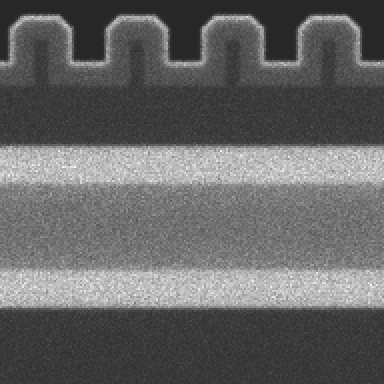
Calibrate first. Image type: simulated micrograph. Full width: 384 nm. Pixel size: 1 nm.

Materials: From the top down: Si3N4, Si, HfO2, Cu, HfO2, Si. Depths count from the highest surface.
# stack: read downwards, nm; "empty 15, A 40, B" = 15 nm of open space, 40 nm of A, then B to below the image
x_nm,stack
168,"empty 46, Si3N4 24, Si 60, HfO2 38, Cu 86, HfO2 38, Si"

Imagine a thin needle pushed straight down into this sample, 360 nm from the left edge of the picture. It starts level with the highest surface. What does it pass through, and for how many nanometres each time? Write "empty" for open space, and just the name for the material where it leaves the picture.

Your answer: empty 46, Si3N4 24, Si 60, HfO2 38, Cu 86, HfO2 38, Si